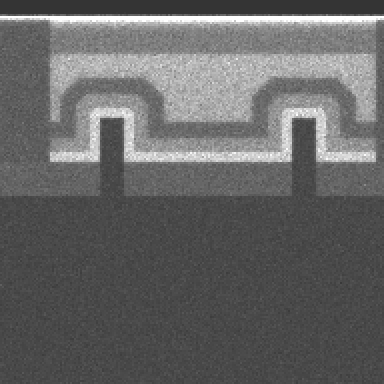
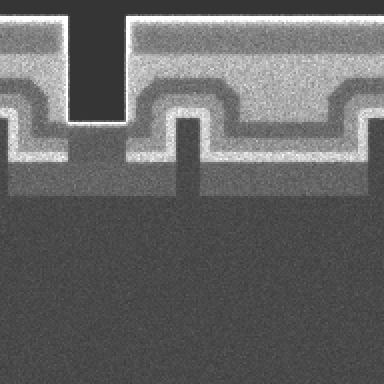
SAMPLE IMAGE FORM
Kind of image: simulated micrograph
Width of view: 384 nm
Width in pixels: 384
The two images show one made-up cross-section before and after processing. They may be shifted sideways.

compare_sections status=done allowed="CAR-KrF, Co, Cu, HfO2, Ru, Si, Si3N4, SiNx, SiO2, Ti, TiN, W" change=removed material="SiNx"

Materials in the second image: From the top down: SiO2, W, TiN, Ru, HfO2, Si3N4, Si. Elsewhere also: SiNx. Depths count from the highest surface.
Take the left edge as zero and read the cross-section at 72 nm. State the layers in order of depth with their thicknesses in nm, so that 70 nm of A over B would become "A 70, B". empty 106, SiNx 40, Si3N4 34, Si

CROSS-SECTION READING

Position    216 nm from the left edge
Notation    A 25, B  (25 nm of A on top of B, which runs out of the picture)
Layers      SiO2 38, W 24, TiN 20, Ru 54, HfO2 10, Si3N4 34, Si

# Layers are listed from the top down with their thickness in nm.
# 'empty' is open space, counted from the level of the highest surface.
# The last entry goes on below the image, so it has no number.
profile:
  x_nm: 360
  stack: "SiO2 38, W 24, TiN 16, Ru 16, HfO2 52, Si3N4 34, Si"